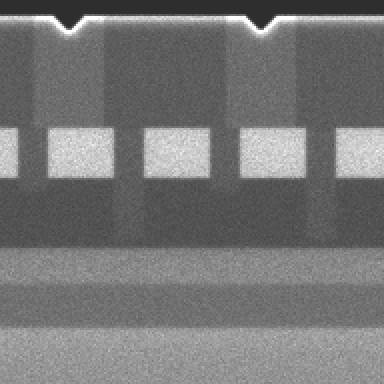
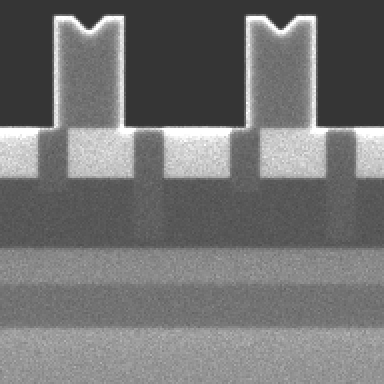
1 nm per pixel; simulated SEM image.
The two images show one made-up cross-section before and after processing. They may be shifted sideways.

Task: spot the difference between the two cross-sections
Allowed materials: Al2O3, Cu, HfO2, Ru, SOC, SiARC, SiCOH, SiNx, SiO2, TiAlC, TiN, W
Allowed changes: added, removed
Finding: removed SOC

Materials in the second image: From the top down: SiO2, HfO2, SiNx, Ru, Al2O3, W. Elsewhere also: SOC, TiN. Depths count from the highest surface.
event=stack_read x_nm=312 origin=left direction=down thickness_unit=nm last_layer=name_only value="SiO2 112, HfO2 50, SiNx 70, Ru 36, Al2O3 44, W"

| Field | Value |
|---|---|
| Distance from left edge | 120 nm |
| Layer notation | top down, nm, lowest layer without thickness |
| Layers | SiO2 112, HfO2 50, SiNx 70, Ru 36, Al2O3 44, W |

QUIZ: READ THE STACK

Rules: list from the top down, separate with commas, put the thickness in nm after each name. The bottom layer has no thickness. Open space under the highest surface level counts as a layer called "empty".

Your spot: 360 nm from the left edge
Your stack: empty 112, HfO2 50, SiNx 70, Ru 36, Al2O3 44, W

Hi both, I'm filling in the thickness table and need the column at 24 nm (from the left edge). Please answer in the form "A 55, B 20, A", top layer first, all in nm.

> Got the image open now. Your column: empty 112, HfO2 50, SiNx 70, Ru 36, Al2O3 44, W